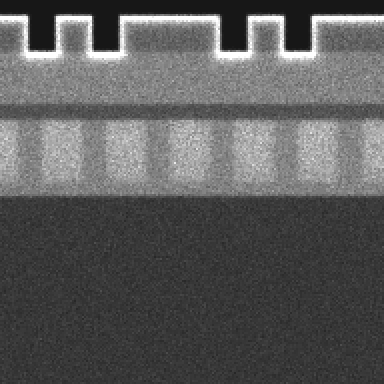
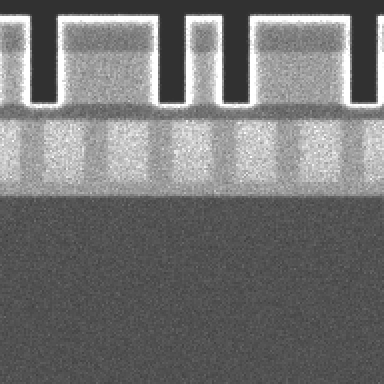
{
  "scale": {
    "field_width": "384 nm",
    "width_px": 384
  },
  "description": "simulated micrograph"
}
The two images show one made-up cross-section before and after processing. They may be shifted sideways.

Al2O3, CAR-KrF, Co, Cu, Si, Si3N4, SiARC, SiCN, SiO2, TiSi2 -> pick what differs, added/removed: SiO2 removed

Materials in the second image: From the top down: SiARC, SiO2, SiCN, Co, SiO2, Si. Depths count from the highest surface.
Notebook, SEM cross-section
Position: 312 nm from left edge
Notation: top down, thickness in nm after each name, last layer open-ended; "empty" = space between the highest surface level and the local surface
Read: SiARC 36, SiO2 52, SiCN 16, Co 62, SiO2 14, Si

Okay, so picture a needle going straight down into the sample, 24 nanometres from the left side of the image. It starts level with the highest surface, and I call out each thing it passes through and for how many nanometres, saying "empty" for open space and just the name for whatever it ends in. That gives SiARC 36, SiO2 52, SiCN 16, SiO2 76, Si